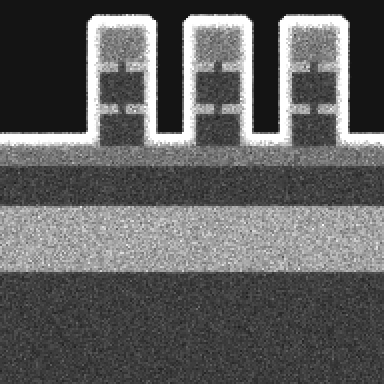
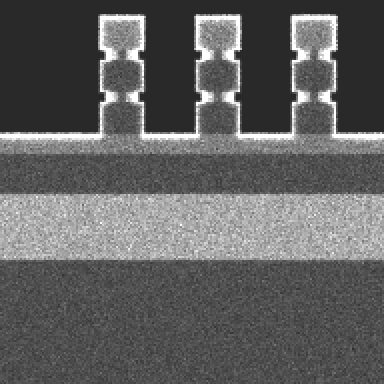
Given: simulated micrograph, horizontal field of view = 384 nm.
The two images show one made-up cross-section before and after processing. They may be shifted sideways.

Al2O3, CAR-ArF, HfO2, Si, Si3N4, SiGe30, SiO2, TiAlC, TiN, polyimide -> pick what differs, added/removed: Al2O3 removed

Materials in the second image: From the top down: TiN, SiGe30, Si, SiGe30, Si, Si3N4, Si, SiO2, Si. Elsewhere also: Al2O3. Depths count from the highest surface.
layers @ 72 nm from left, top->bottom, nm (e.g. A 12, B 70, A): empty 118, Si3N4 20, Si 40, SiO2 66, Si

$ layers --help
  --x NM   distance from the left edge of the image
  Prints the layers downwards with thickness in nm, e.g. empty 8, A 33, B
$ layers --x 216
TiN 34, SiGe30 10, Si 32, SiGe30 10, Si 32, Si3N4 20, Si 40, SiO2 66, Si